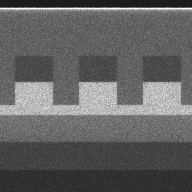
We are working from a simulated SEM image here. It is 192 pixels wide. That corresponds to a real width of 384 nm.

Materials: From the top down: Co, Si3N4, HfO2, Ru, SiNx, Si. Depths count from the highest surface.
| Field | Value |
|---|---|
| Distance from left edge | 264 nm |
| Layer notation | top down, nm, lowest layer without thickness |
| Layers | Co 194, HfO2 20, Ru 54, SiNx 56, Si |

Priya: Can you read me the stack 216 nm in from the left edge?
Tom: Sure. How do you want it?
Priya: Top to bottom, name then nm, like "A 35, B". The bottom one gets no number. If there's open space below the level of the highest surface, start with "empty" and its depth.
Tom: Co 96, Si3N4 52, HfO2 66, Ru 54, SiNx 56, Si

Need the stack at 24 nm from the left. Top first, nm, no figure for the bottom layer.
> Co 194, HfO2 20, Ru 54, SiNx 56, Si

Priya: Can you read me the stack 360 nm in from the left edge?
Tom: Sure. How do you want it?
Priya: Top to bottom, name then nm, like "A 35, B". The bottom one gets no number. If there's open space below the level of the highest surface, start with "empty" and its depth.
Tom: Co 96, Si3N4 52, HfO2 66, Ru 54, SiNx 56, Si